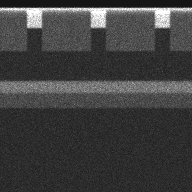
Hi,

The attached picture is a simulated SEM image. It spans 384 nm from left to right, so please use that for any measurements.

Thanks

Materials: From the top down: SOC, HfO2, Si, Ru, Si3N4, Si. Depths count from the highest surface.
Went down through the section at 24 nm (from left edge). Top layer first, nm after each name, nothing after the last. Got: SOC 86, Si 60, Ru 24, Si3N4 30, Si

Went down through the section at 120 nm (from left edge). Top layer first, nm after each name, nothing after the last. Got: SOC 86, Si 60, Ru 24, Si3N4 30, Si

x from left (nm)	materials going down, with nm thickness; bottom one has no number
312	SOC 6, HfO2 34, Si 106, Ru 24, Si3N4 30, Si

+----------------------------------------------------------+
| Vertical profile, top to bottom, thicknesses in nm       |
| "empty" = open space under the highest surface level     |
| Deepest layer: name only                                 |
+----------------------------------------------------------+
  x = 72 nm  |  SOC 6, HfO2 34, Si 106, Ru 24, Si3N4 30, Si